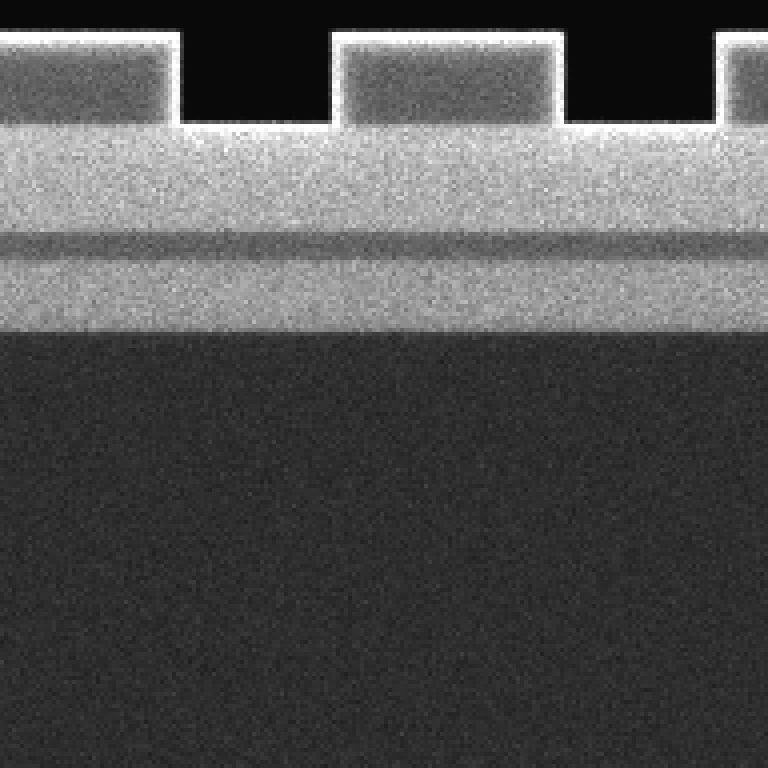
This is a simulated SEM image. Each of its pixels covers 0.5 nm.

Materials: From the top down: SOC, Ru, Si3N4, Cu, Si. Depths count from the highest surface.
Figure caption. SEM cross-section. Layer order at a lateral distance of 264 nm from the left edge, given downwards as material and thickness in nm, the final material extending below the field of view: SOC 46, Ru 54, Si3N4 14, Cu 36, Si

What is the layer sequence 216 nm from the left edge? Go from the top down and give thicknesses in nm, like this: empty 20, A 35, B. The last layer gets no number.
SOC 46, Ru 54, Si3N4 14, Cu 36, Si